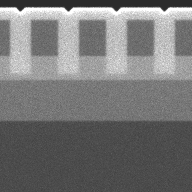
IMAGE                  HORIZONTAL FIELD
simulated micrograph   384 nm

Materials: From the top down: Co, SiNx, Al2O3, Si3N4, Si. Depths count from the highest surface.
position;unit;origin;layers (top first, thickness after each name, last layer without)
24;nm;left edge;Co 132, Al2O3 12, Si3N4 82, Si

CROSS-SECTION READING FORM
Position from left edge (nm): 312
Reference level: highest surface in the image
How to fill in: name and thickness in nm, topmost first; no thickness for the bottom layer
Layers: Co 132, Al2O3 12, Si3N4 82, Si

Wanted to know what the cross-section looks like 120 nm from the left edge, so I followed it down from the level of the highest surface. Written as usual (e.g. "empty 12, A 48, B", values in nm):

Co 132, Al2O3 12, Si3N4 82, Si